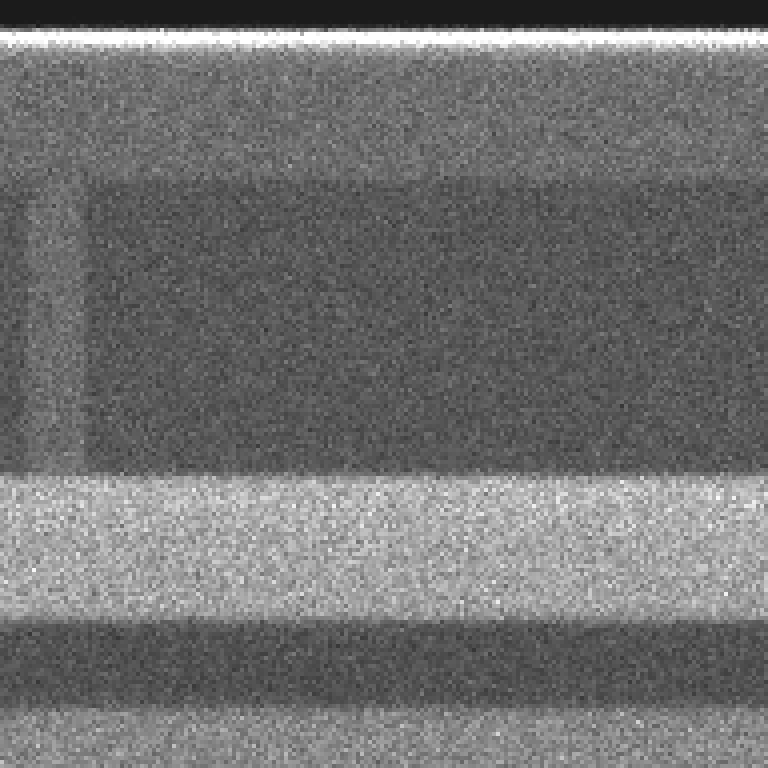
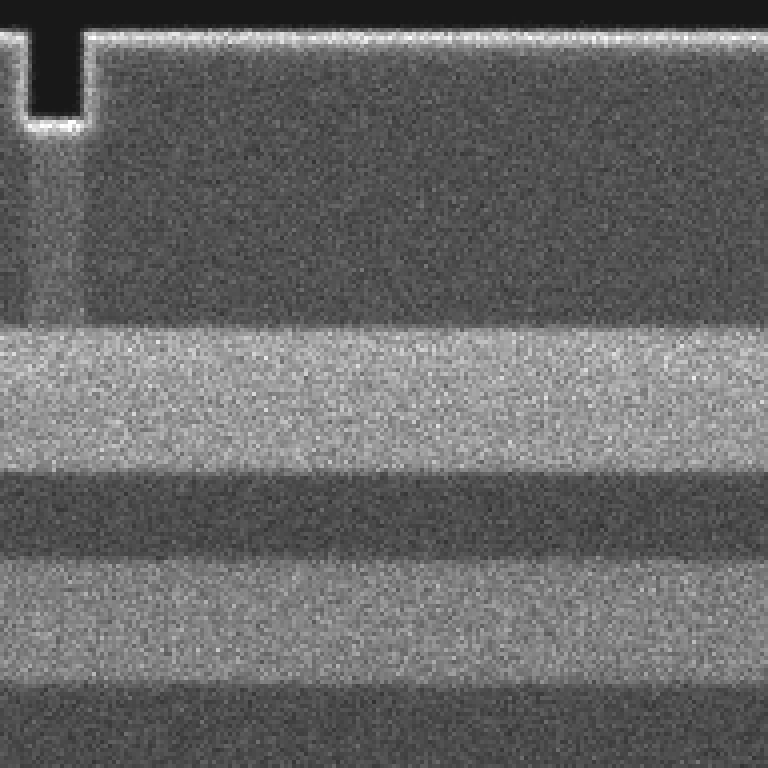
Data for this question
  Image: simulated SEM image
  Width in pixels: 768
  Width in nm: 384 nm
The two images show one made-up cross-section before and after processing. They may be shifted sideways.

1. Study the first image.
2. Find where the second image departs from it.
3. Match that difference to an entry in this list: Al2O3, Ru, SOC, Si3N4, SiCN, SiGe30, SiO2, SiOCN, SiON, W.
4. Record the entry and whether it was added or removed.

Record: SiO2 / removed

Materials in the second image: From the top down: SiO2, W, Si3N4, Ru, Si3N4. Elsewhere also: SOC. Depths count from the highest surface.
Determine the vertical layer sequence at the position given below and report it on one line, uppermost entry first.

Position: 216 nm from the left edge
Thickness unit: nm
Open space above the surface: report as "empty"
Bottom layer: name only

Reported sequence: SOC 148, W 72, Si3N4 44, Ru 62, Si3N4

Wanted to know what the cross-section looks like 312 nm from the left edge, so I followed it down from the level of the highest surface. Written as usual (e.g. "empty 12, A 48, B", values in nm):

SOC 148, W 72, Si3N4 44, Ru 62, Si3N4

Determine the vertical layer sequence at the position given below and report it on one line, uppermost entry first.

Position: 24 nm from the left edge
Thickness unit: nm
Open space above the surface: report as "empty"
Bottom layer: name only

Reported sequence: empty 44, SiO2 104, W 72, Si3N4 44, Ru 62, Si3N4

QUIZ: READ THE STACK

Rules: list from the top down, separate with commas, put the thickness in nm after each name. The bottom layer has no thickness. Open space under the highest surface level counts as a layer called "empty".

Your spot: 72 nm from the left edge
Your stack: SOC 148, W 72, Si3N4 44, Ru 62, Si3N4